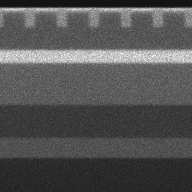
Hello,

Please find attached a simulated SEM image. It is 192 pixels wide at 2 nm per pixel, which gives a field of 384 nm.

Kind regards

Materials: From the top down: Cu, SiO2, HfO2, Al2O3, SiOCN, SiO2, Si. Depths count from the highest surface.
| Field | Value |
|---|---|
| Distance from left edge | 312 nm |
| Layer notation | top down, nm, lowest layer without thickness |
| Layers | Cu 38, SiO2 46, HfO2 26, Al2O3 84, SiOCN 66, SiO2 40, Si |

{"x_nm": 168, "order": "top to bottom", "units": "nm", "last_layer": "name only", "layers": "SiO2 84, HfO2 26, Al2O3 84, SiOCN 66, SiO2 40, Si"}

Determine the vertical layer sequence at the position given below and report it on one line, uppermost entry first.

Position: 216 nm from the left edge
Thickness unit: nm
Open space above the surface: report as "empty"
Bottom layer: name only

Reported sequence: SiO2 84, HfO2 26, Al2O3 84, SiOCN 66, SiO2 40, Si